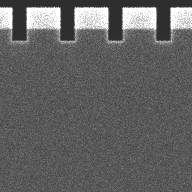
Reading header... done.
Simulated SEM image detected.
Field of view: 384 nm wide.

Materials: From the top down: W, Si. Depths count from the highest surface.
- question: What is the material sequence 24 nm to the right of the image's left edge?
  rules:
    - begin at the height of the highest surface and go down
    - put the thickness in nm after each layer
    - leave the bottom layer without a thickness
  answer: empty 66, Si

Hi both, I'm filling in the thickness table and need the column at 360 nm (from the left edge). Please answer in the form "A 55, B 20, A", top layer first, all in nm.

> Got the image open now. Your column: W 42, Si